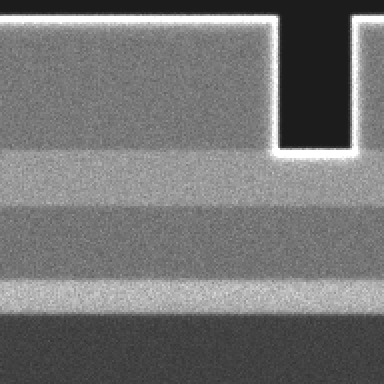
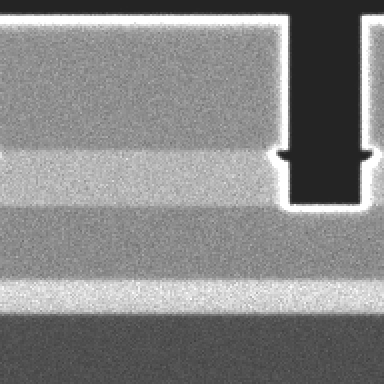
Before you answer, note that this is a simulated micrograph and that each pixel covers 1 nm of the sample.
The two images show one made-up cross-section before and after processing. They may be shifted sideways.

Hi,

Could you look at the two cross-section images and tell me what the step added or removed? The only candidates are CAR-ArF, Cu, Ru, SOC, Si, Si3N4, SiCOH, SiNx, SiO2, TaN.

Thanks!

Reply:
removed SiO2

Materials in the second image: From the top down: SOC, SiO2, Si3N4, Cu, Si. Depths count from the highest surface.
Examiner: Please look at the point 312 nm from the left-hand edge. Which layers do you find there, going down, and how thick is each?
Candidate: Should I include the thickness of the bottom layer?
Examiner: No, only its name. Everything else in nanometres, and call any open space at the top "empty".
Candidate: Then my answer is empty 190, Si3N4 74, Cu 34, Si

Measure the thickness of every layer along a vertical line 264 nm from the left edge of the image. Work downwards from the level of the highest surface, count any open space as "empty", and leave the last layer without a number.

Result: SOC 134, SiO2 56, Si3N4 74, Cu 34, Si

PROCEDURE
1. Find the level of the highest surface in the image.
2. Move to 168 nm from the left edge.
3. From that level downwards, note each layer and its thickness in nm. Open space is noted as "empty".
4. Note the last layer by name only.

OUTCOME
SOC 134, SiO2 56, Si3N4 74, Cu 34, Si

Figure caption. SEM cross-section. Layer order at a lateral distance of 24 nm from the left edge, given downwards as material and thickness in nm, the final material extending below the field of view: SOC 134, SiO2 56, Si3N4 74, Cu 34, Si